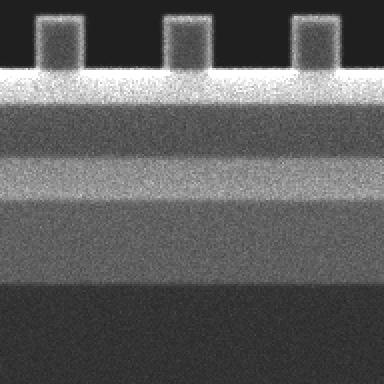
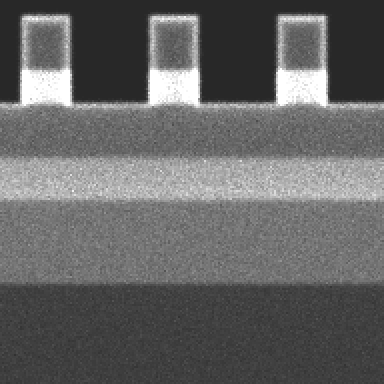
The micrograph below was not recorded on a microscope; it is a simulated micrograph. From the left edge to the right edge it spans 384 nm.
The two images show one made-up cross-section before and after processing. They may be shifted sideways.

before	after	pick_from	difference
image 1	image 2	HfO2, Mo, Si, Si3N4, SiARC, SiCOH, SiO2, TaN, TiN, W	HfO2 removed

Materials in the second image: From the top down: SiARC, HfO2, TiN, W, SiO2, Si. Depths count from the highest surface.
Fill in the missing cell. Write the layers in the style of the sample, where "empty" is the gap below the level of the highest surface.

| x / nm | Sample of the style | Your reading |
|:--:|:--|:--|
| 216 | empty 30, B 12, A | empty 88, TiN 54, W 42, SiO2 84, Si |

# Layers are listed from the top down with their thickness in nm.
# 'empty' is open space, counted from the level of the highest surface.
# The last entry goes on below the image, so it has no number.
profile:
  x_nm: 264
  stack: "empty 88, TiN 54, W 42, SiO2 84, Si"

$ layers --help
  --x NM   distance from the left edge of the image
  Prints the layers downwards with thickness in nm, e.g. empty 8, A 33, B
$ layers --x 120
empty 88, TiN 54, W 42, SiO2 84, Si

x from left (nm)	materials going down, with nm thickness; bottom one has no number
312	SiARC 54, HfO2 34, TiN 54, W 42, SiO2 84, Si